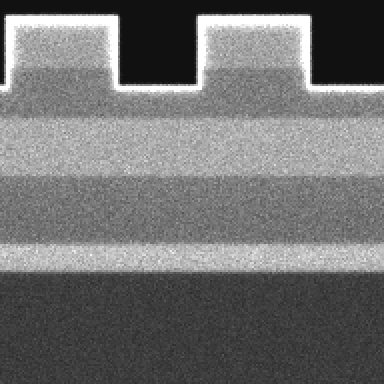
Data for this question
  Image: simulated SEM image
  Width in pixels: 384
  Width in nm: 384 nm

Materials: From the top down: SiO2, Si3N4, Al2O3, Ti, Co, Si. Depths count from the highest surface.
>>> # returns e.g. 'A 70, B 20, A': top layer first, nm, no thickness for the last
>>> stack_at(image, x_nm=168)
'empty 70, Si3N4 32, Al2O3 58, Ti 68, Co 28, Si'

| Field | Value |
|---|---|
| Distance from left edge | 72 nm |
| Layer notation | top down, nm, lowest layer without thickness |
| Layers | SiO2 52, Si3N4 50, Al2O3 58, Ti 68, Co 28, Si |